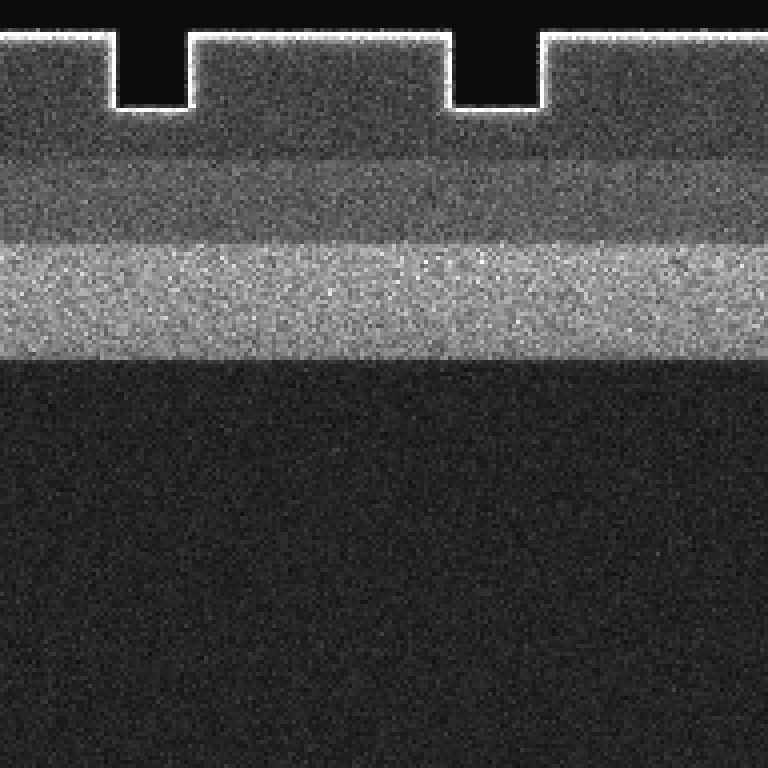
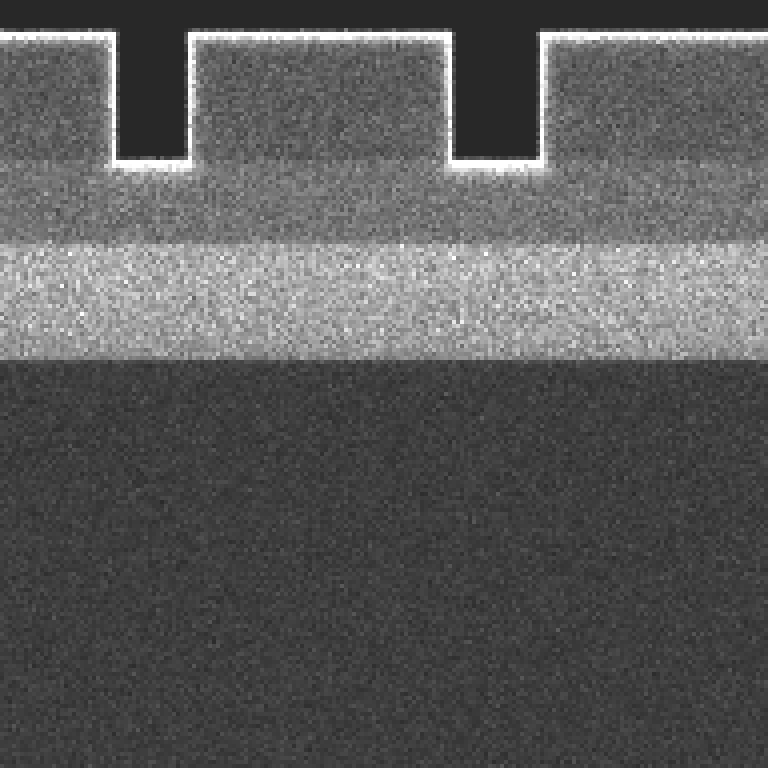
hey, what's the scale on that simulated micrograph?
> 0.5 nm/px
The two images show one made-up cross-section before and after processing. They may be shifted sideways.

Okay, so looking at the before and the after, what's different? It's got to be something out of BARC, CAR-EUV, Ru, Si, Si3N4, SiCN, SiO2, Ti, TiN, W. TiN, removed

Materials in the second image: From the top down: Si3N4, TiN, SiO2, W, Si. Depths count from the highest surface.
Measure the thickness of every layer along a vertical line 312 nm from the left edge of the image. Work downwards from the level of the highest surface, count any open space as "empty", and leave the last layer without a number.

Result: Si3N4 38, TiN 26, SiO2 42, W 58, Si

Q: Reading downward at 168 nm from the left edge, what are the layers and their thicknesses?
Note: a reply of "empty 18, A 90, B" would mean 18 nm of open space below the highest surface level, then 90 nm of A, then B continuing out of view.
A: Si3N4 38, TiN 26, SiO2 42, W 58, Si